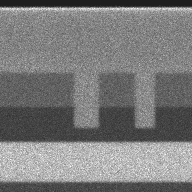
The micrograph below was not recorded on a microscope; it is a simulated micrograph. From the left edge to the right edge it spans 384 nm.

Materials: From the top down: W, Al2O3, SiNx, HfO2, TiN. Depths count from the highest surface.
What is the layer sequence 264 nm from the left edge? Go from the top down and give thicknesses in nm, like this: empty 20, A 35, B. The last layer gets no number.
W 130, Al2O3 68, SiNx 70, HfO2 80, TiN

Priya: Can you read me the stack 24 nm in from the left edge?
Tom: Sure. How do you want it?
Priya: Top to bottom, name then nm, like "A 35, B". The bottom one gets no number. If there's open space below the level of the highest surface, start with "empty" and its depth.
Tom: W 130, Al2O3 68, SiNx 70, HfO2 80, TiN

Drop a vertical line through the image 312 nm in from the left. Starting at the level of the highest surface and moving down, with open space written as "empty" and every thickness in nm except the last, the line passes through W 130, Al2O3 68, SiNx 70, HfO2 80, TiN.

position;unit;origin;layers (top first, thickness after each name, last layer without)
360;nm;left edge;W 130, Al2O3 68, SiNx 70, HfO2 80, TiN